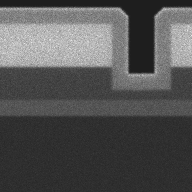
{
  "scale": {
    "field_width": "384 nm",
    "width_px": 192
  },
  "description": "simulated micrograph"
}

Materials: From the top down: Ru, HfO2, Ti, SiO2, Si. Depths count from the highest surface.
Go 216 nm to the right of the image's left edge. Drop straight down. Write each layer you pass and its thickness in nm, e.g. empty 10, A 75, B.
Ru 32, HfO2 86, Ti 66, SiO2 32, Si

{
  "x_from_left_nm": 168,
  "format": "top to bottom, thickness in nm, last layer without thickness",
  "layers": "Ru 32, HfO2 86, Ti 66, SiO2 32, Si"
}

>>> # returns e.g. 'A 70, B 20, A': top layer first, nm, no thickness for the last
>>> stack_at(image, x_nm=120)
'Ru 32, HfO2 86, Ti 66, SiO2 32, Si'